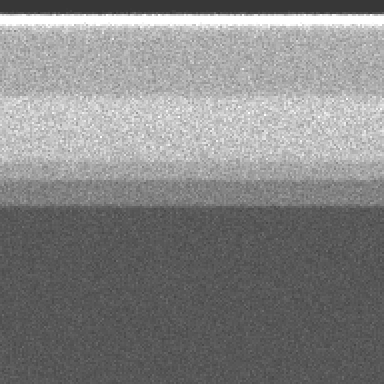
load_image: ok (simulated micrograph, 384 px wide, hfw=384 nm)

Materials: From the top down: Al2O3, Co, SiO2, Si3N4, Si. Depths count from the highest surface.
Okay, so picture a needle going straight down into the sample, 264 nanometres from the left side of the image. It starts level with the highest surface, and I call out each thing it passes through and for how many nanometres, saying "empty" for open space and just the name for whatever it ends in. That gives Al2O3 80, Co 66, SiO2 18, Si3N4 26, Si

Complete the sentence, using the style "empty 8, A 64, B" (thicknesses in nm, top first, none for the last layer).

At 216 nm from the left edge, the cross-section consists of Al2O3 80, Co 66, SiO2 18, Si3N4 26, Si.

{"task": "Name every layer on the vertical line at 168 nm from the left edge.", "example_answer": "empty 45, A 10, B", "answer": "Al2O3 80, Co 66, SiO2 18, Si3N4 26, Si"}